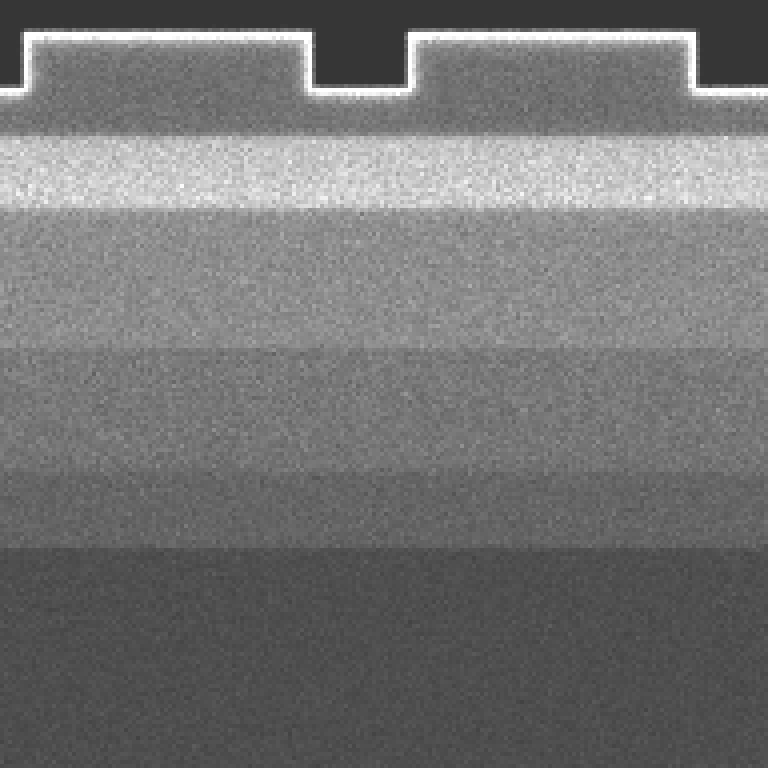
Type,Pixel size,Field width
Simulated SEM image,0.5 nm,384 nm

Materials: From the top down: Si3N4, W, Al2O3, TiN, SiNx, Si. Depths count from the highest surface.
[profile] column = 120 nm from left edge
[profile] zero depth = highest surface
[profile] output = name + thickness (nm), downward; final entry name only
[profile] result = Si3N4 52, W 36, Al2O3 70, TiN 62, SiNx 38, Si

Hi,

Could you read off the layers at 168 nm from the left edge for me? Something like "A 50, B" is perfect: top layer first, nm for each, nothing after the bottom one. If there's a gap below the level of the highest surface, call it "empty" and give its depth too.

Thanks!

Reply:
empty 28, Si3N4 24, W 36, Al2O3 70, TiN 62, SiNx 38, Si